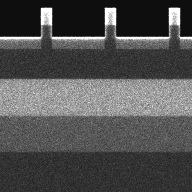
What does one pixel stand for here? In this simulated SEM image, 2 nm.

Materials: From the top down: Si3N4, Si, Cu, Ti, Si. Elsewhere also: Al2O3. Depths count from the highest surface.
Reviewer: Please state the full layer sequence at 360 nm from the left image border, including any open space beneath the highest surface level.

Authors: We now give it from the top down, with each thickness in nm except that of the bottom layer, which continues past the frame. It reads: empty 58, Si3N4 24, Si 60, Cu 74, Ti 72, Si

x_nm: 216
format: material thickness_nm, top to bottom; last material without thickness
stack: Al2O3 34, Si 108, Cu 74, Ti 72, Si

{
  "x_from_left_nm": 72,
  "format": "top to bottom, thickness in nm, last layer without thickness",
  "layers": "empty 58, Si3N4 24, Si 60, Cu 74, Ti 72, Si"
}